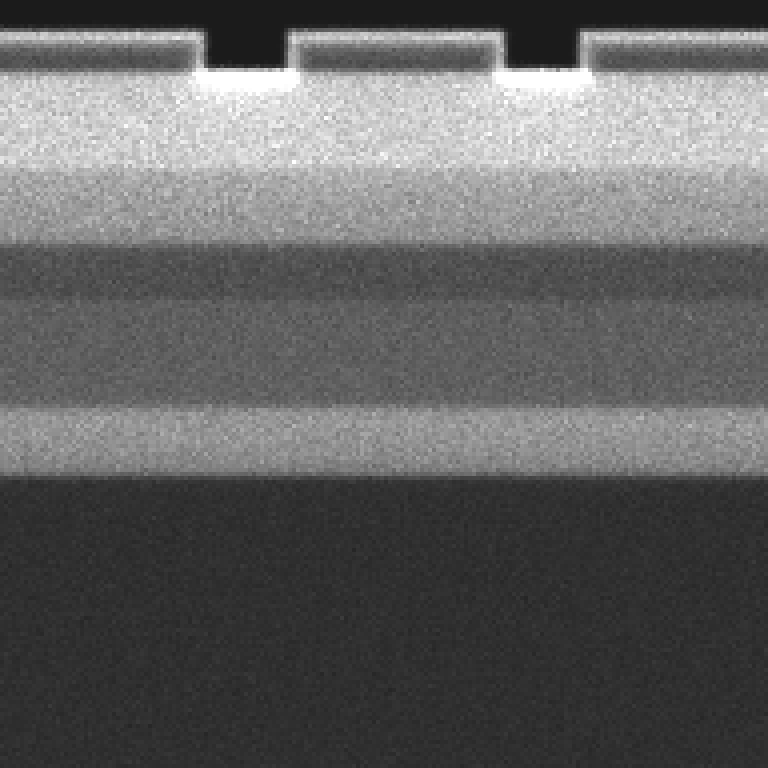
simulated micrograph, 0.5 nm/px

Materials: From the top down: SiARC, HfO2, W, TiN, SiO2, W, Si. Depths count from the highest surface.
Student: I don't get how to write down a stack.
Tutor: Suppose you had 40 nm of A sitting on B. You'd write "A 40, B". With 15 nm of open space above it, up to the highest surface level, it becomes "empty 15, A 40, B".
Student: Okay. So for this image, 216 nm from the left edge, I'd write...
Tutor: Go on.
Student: SiARC 20, HfO2 48, W 38, TiN 28, SiO2 54, W 34, Si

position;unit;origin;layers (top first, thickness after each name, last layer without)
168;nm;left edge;SiARC 20, HfO2 48, W 38, TiN 28, SiO2 54, W 34, Si